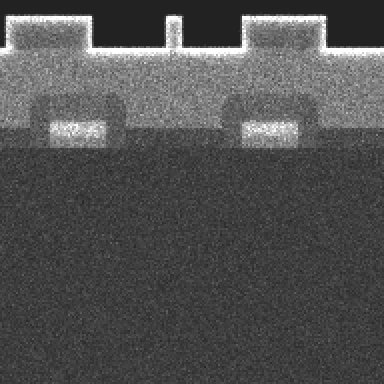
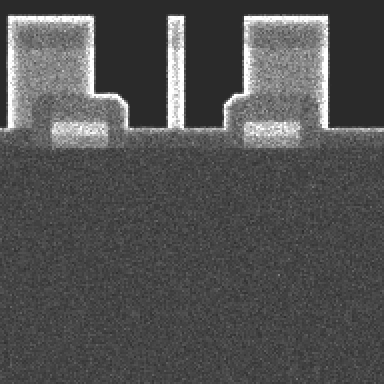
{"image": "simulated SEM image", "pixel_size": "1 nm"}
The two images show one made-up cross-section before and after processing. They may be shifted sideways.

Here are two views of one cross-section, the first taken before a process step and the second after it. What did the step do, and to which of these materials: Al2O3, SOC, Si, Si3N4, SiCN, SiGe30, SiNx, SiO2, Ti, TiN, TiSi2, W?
It removed SiO2.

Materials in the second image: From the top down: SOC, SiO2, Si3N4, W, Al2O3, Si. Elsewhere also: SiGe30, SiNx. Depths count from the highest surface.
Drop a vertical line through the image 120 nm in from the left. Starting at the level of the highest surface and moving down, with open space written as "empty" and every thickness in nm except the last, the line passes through empty 82, SiNx 50, Si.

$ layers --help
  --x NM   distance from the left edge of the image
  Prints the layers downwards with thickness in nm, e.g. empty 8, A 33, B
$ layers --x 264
SOC 32, SiO2 46, Si3N4 28, W 14, Al2O3 12, Si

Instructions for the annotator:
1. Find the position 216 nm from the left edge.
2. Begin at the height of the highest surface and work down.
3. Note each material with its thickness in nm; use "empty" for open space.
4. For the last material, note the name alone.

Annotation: empty 112, SiGe30 20, Si